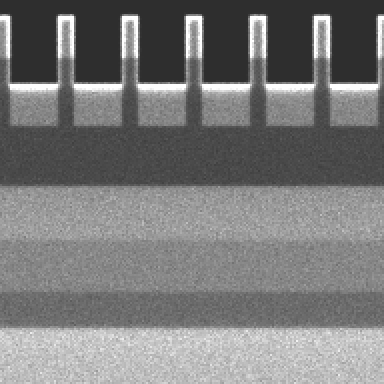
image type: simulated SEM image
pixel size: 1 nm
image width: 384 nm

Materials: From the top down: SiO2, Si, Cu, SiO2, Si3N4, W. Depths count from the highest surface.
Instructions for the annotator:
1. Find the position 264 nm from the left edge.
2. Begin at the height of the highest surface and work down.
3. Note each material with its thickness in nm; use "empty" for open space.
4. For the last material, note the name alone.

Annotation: Si3N4 42, Si 128, Cu 54, SiO2 52, Si3N4 36, W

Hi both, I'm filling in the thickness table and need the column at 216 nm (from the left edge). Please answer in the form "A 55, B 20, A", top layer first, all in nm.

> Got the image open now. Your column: empty 68, SiO2 42, Si 60, Cu 54, SiO2 52, Si3N4 36, W